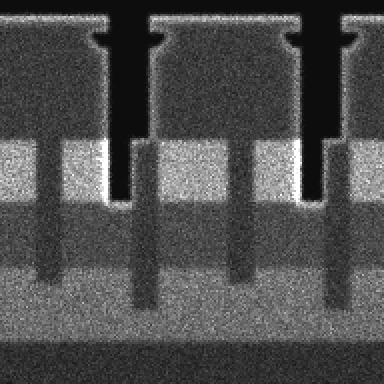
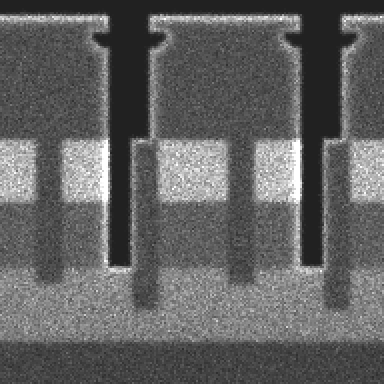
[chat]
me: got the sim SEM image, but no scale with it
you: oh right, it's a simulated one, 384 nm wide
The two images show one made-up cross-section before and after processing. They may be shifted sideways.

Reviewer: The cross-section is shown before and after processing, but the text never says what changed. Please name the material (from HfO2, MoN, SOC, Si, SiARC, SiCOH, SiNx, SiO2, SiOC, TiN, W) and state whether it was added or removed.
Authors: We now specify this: SiO2, removed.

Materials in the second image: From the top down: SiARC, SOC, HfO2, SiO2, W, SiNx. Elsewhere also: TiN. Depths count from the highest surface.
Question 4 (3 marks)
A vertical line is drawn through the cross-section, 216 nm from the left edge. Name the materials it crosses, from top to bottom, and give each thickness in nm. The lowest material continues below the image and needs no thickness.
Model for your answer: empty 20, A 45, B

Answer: SiARC 16, SOC 108, HfO2 62, SiO2 66, W 74, SiNx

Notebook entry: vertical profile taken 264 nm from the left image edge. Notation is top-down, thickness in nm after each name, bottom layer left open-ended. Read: SiARC 16, SOC 108, HfO2 62, SiO2 66, W 74, SiNx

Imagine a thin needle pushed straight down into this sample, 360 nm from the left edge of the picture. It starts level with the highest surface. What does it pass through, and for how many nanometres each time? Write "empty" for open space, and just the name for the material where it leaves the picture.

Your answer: SiARC 16, SOC 108, HfO2 62, SiO2 66, W 74, SiNx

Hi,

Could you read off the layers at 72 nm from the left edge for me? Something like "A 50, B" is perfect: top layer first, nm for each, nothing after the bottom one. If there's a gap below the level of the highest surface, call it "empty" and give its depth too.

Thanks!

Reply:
SiARC 16, SOC 108, HfO2 62, SiO2 66, W 74, SiNx